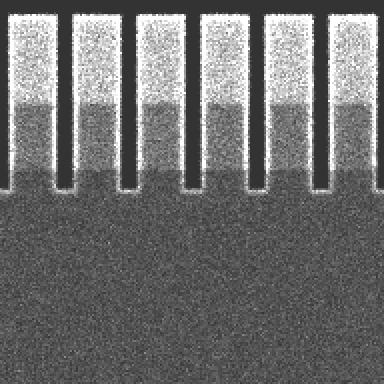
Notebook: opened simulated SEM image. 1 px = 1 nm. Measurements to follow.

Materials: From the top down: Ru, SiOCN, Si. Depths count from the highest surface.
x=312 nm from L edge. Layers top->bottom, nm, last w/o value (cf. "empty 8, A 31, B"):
empty 174, Si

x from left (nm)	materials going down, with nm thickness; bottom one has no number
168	Ru 88, SiOCN 66, Si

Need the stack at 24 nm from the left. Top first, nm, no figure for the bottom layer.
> Ru 88, SiOCN 66, Si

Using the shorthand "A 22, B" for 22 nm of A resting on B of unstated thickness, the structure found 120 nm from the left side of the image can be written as empty 174, Si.